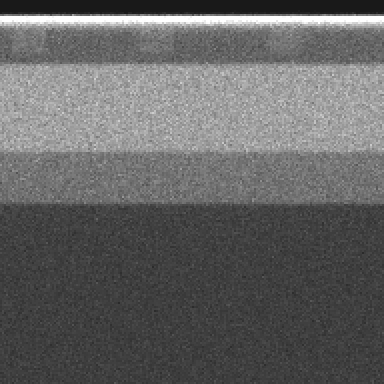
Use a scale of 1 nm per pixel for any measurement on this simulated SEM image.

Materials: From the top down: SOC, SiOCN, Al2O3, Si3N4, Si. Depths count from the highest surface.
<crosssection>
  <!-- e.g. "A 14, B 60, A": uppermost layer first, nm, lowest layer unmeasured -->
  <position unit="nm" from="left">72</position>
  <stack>SOC 8, SiOCN 40, Al2O3 88, Si3N4 52, Si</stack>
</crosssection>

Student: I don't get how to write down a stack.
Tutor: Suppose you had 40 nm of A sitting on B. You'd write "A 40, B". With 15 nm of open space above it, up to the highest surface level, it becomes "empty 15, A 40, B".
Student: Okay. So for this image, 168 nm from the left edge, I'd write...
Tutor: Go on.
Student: SOC 36, SiOCN 12, Al2O3 88, Si3N4 52, Si